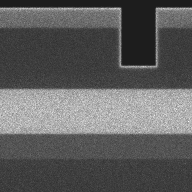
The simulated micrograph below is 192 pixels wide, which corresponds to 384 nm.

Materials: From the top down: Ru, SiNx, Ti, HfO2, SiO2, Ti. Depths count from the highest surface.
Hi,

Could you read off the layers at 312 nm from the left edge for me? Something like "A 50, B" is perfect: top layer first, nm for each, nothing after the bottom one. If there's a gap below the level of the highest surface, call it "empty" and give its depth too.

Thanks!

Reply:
Ru 40, SiNx 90, Ti 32, HfO2 90, SiO2 50, Ti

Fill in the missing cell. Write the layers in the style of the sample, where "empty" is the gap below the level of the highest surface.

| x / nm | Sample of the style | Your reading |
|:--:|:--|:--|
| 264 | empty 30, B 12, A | empty 116, SiNx 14, Ti 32, HfO2 90, SiO2 50, Ti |